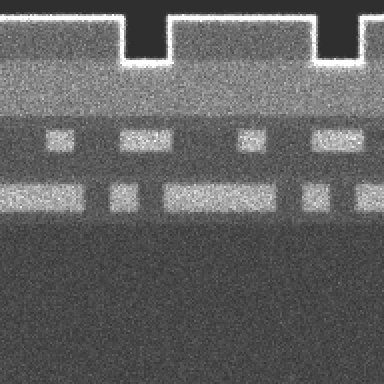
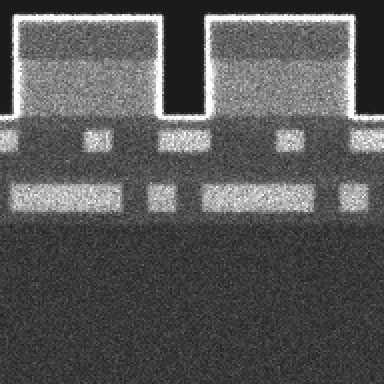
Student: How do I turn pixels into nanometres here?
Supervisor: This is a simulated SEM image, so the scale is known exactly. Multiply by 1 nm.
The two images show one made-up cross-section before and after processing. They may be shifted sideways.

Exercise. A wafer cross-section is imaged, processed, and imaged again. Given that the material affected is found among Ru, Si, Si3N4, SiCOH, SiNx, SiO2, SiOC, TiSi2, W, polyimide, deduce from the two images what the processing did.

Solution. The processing removed SiO2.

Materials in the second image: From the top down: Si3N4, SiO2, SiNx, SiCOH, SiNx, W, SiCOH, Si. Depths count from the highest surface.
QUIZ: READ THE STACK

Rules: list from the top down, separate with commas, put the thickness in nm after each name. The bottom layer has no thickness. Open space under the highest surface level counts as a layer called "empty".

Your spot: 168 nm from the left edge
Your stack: empty 100, SiNx 14, W 22, SiCOH 24, SiNx 8, W 28, SiCOH 12, Si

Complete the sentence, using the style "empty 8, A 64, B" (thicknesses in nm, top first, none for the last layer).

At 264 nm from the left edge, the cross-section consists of Si3N4 44, SiO2 56, SiNx 14, SiCOH 46, SiNx 8, W 28, SiCOH 12, Si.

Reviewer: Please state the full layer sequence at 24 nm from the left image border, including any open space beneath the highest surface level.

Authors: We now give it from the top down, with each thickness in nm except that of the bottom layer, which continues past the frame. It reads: Si3N4 44, SiO2 56, SiNx 14, SiCOH 46, SiNx 8, W 28, SiCOH 12, Si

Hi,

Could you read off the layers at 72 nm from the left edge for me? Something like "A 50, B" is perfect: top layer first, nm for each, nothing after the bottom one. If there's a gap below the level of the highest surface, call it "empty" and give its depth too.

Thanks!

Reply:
Si3N4 44, SiO2 56, SiNx 14, SiCOH 46, SiNx 8, W 28, SiCOH 12, Si